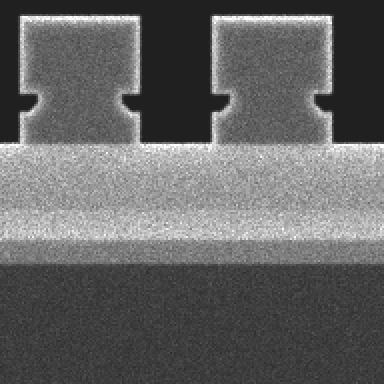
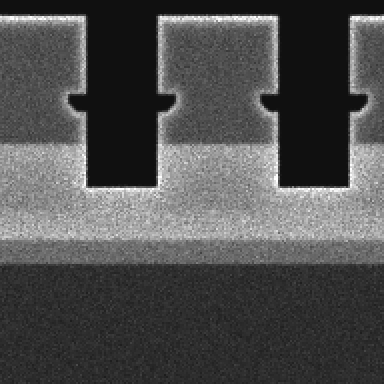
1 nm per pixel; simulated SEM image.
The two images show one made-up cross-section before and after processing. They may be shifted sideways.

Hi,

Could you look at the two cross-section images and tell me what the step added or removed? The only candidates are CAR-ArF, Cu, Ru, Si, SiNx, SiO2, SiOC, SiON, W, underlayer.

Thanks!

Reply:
removed Ru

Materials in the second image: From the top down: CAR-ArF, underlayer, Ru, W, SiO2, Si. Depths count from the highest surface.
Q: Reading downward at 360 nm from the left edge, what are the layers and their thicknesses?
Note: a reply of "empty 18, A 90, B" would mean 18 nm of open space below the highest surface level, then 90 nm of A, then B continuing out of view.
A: CAR-ArF 78, empty 16, underlayer 34, Ru 66, W 30, SiO2 24, Si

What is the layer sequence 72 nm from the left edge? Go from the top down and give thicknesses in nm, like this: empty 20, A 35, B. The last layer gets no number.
CAR-ArF 78, empty 14, underlayer 36, Ru 66, W 30, SiO2 24, Si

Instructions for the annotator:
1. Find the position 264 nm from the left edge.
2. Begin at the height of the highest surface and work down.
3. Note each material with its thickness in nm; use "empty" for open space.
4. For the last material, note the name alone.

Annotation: CAR-ArF 78, empty 14, underlayer 36, Ru 66, W 30, SiO2 24, Si